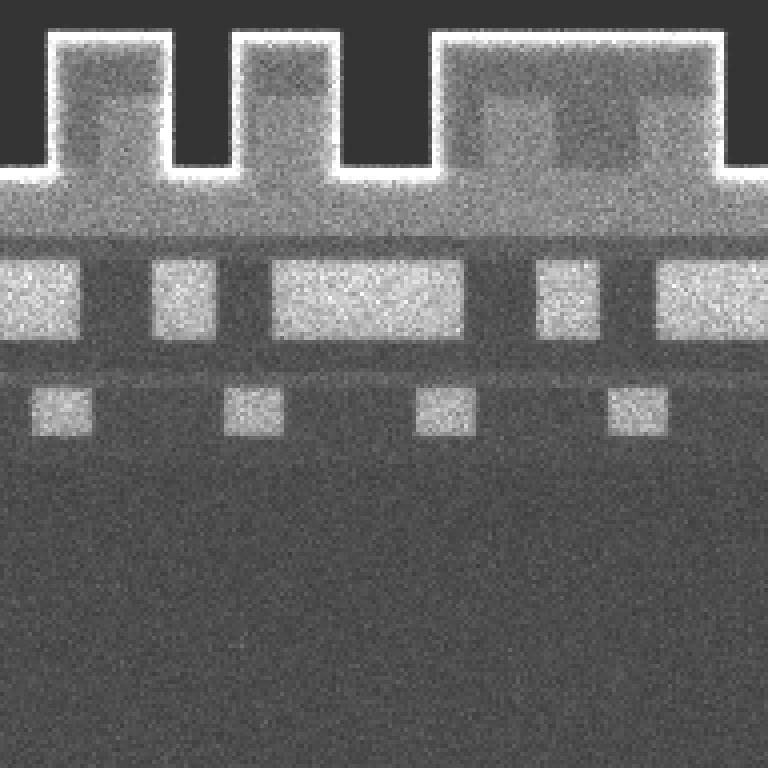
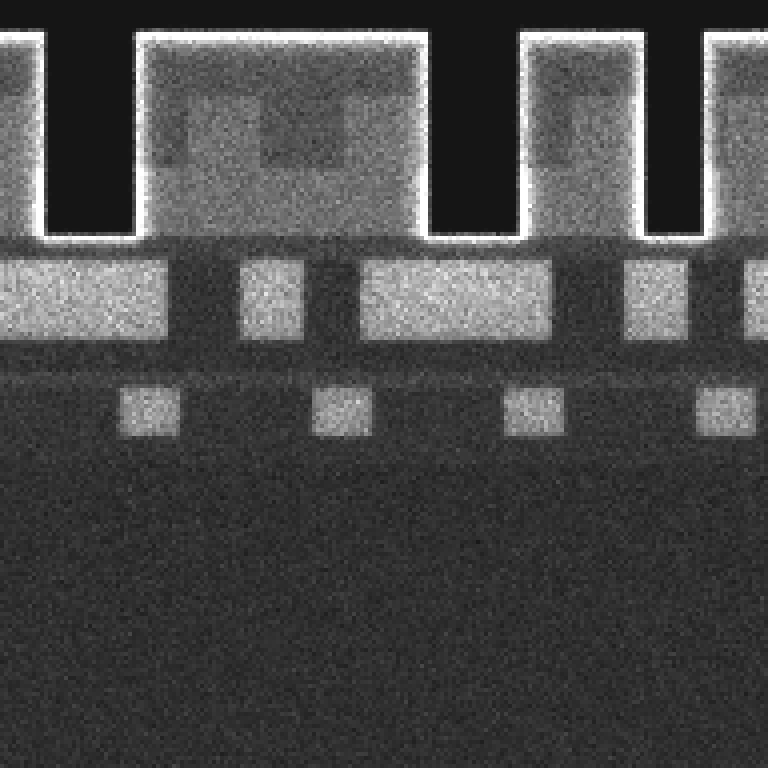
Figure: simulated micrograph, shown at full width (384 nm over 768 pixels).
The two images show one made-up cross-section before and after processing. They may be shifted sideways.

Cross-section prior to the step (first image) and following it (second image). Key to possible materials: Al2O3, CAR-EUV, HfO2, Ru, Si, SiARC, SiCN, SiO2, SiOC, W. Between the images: SiO2 was removed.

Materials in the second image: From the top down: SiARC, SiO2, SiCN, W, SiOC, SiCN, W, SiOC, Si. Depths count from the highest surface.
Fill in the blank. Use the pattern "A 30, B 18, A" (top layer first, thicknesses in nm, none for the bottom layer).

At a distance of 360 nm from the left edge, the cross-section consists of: SiARC 68, SiO2 34, SiCN 12, SiOC 56, SiCN 8, W 24, SiOC 14, Si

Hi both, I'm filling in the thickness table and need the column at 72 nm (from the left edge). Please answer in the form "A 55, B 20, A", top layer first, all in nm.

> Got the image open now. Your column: SiARC 68, SiO2 34, SiCN 12, W 40, SiOC 16, SiCN 8, W 24, SiOC 14, Si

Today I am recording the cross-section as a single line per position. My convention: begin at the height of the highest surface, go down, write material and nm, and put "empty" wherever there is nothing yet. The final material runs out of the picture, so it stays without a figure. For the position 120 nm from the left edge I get SiARC 32, SiO2 70, SiCN 12, W 40, SiOC 16, SiCN 8, SiOC 38, Si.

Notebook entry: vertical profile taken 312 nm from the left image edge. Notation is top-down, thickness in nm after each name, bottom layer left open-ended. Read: SiARC 32, SiO2 70, SiCN 12, W 40, SiOC 16, SiCN 8, SiOC 38, Si